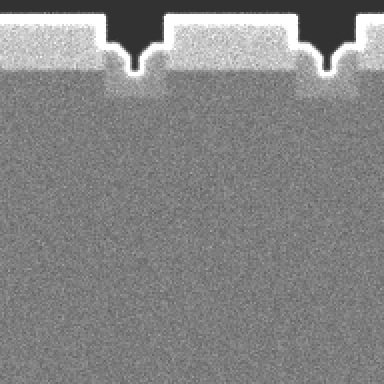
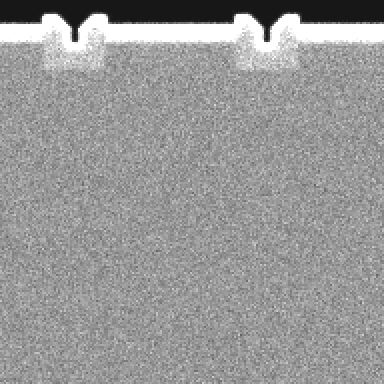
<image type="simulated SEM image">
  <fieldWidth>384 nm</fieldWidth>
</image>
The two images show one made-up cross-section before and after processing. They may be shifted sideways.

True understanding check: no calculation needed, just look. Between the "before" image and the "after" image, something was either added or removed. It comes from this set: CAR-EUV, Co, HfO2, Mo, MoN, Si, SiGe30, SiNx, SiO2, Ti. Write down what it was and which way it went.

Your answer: SiNx (removed)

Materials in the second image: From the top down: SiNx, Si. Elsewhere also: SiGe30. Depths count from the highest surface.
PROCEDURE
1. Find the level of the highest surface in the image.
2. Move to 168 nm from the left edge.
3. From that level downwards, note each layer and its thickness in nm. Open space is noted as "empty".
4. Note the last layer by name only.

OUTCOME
empty 10, SiNx 16, Si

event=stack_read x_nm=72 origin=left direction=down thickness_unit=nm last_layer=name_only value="empty 28, SiGe30 26, Si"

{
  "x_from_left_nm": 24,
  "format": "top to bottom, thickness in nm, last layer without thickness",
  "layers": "empty 10, SiNx 16, Si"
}